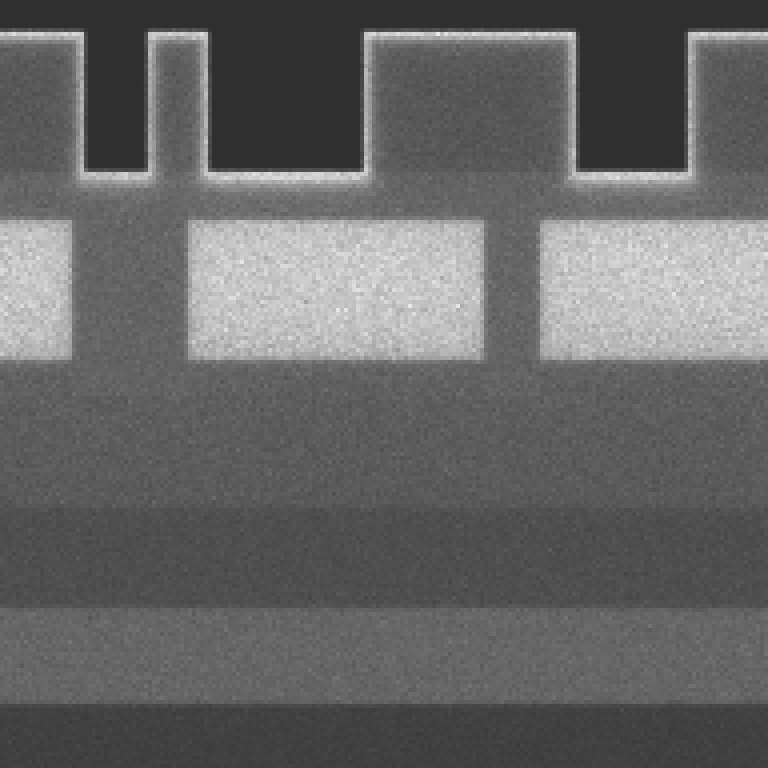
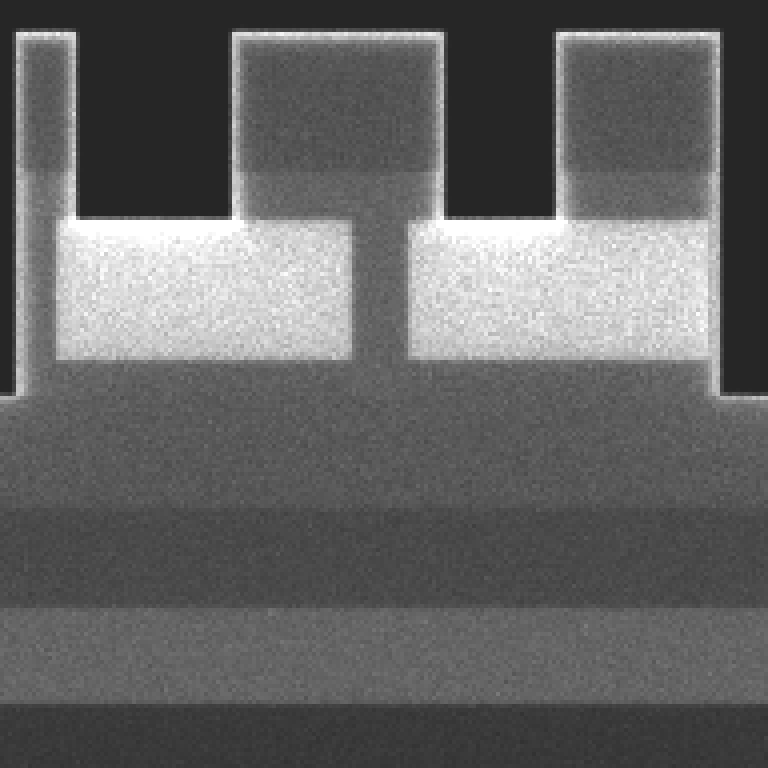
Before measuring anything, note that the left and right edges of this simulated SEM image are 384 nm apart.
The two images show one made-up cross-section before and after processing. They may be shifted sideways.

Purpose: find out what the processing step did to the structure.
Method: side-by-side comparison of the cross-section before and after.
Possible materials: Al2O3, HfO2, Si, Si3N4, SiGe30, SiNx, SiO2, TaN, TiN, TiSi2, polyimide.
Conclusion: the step removed SiO2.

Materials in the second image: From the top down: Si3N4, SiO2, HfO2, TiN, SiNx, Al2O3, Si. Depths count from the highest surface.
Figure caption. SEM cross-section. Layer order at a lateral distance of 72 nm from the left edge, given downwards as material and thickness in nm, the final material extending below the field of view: empty 94, HfO2 70, TiN 74, SiNx 50, Al2O3 48, Si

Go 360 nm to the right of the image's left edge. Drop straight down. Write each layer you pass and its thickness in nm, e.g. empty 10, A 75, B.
empty 182, TiN 56, SiNx 50, Al2O3 48, Si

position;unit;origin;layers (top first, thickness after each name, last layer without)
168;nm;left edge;Si3N4 70, SiO2 24, HfO2 70, TiN 74, SiNx 50, Al2O3 48, Si